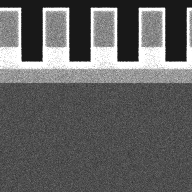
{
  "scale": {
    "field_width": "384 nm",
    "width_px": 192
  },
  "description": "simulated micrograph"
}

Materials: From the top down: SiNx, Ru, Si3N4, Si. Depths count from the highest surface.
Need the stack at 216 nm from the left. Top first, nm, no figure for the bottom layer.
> SiNx 78, Ru 44, Si3N4 28, Si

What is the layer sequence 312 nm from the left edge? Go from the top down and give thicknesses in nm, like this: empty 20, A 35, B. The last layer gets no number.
SiNx 78, Ru 44, Si3N4 28, Si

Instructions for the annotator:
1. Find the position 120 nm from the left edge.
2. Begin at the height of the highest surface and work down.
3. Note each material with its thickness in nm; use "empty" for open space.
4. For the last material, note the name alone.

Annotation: SiNx 78, Ru 44, Si3N4 28, Si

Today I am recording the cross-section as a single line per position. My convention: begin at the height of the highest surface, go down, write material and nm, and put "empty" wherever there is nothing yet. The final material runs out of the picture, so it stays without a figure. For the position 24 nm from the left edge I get SiNx 78, Ru 44, Si3N4 28, Si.